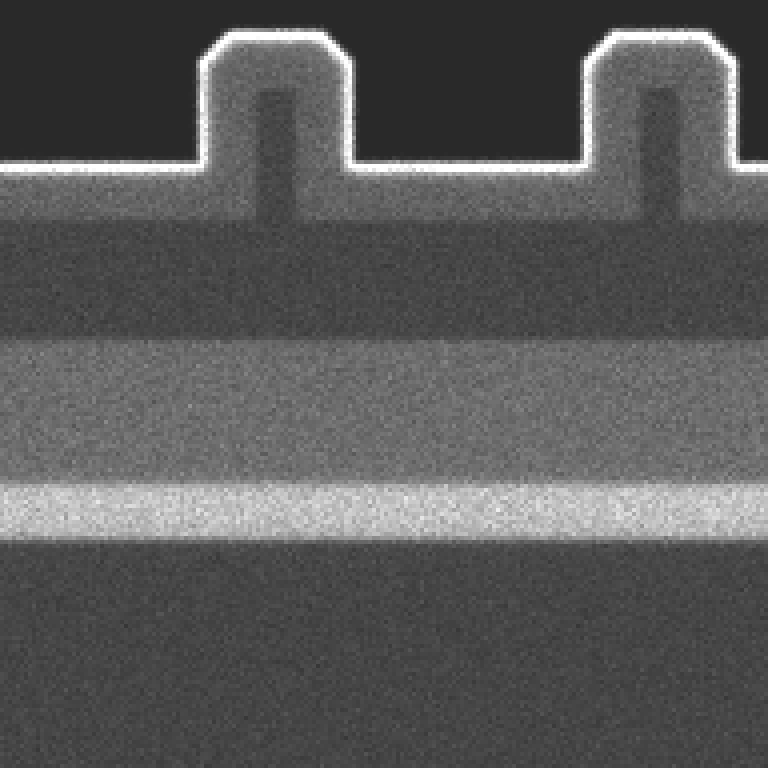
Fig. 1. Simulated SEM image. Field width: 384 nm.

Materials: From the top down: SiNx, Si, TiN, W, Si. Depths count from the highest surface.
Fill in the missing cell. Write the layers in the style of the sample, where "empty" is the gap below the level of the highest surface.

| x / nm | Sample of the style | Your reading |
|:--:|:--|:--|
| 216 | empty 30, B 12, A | empty 66, SiNx 28, Si 60, TiN 72, W 28, Si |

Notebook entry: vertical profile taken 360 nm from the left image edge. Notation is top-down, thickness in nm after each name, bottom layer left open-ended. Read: empty 8, SiNx 86, Si 60, TiN 72, W 28, Si